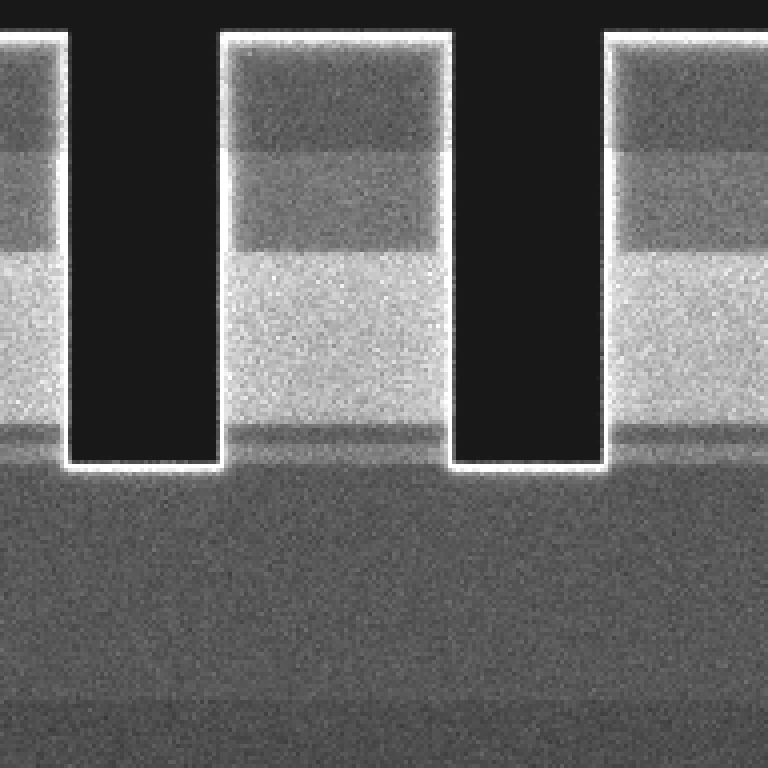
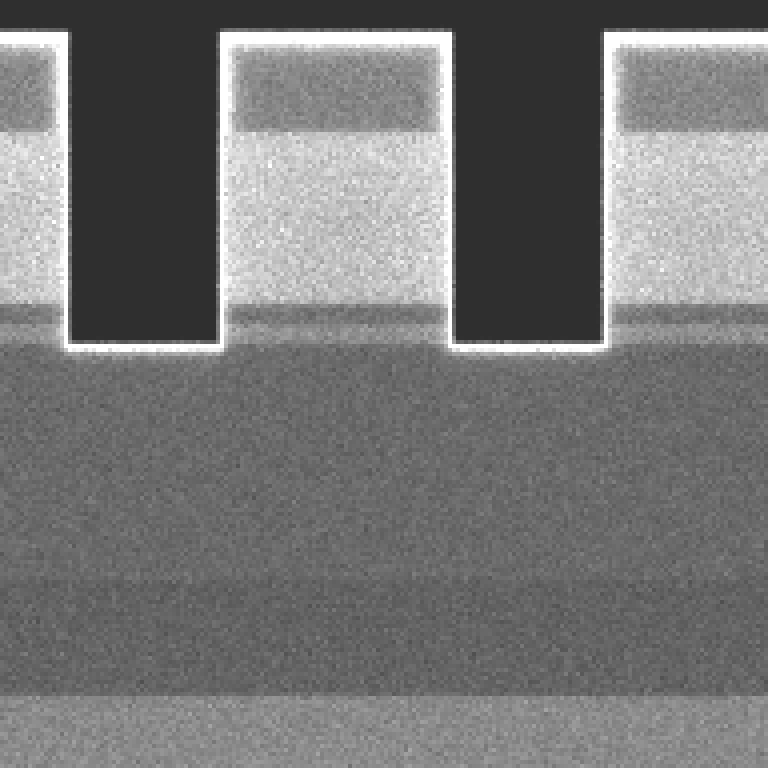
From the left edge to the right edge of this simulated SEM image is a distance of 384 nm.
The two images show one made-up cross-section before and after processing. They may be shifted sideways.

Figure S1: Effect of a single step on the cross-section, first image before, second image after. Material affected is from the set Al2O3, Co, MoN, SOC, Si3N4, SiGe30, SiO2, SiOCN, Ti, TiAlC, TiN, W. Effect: removed SOC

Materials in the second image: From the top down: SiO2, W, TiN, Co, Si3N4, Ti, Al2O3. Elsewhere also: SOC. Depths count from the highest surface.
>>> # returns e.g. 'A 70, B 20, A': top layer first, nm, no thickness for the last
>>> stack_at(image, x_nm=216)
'SiO2 50, W 86, TiN 10, Co 10, Si3N4 118, Ti 58, Al2O3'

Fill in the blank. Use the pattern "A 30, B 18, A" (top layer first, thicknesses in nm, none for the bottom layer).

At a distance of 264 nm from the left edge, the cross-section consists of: empty 156, Si3N4 118, Ti 58, Al2O3